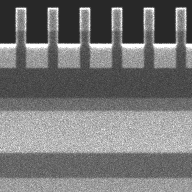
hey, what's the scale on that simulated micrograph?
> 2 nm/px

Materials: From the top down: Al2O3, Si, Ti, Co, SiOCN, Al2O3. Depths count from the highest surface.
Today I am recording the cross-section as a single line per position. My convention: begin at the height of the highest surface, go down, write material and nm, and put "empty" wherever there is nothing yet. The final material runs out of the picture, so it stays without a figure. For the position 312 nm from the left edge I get empty 72, Al2O3 48, Si 60, Ti 26, Co 84, SiOCN 50, Al2O3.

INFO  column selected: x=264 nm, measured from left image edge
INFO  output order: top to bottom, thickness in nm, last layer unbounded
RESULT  empty 72, Al2O3 48, Si 60, Ti 26, Co 84, SiOCN 50, Al2O3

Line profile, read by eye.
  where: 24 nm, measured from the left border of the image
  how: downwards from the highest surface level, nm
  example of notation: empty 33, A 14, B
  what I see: empty 72, Al2O3 48, Si 60, Ti 26, Co 84, SiOCN 50, Al2O3